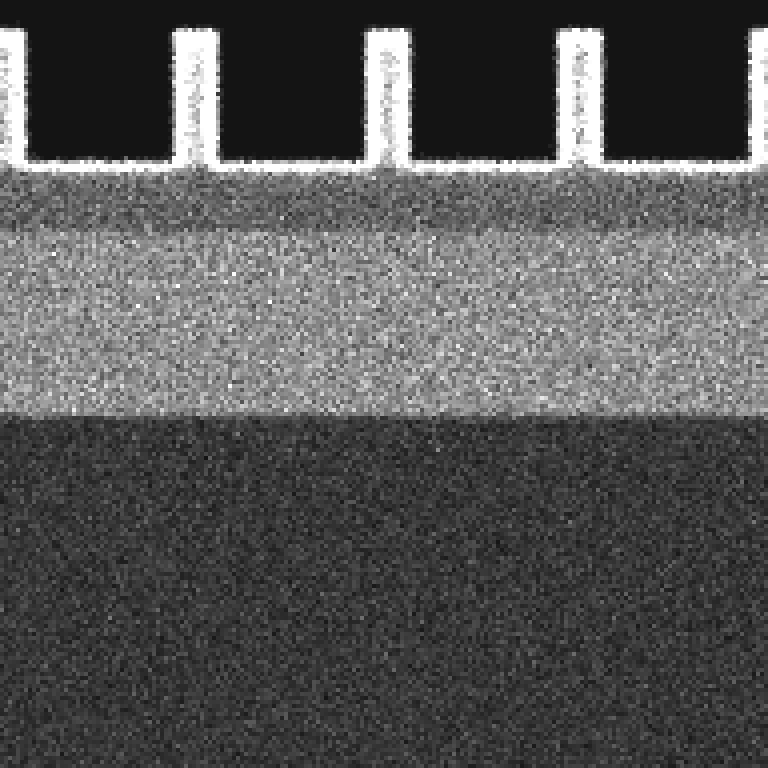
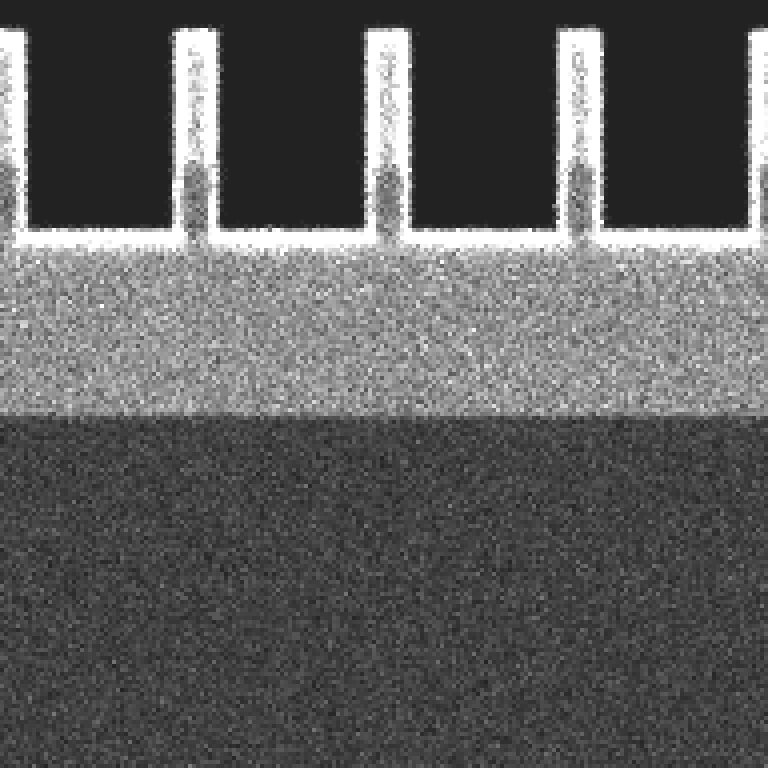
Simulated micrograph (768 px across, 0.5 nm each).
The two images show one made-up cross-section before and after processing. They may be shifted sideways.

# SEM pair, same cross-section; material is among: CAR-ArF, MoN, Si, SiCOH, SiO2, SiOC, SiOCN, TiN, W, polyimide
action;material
removed;TiN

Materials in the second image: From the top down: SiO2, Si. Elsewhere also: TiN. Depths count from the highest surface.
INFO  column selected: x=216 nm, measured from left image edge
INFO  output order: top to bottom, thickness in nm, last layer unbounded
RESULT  empty 100, SiO2 92, Si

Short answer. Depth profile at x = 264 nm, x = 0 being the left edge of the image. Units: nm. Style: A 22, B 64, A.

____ empty 100, SiO2 92, Si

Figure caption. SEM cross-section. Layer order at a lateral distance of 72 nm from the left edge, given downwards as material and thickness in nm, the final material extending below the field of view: empty 100, SiO2 92, Si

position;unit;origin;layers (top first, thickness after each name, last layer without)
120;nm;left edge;empty 100, SiO2 92, Si